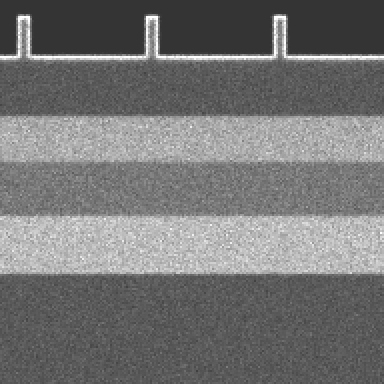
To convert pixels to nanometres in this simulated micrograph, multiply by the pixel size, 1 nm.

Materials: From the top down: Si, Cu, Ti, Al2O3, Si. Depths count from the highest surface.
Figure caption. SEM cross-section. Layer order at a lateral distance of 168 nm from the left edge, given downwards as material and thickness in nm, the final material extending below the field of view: empty 40, Si 60, Cu 46, Ti 54, Al2O3 58, Si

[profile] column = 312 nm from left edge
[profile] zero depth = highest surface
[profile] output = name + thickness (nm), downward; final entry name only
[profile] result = empty 40, Si 60, Cu 46, Ti 54, Al2O3 58, Si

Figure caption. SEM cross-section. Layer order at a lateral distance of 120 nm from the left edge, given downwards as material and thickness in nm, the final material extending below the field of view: empty 40, Si 60, Cu 46, Ti 54, Al2O3 58, Si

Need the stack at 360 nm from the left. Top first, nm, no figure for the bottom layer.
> empty 40, Si 60, Cu 46, Ti 54, Al2O3 58, Si